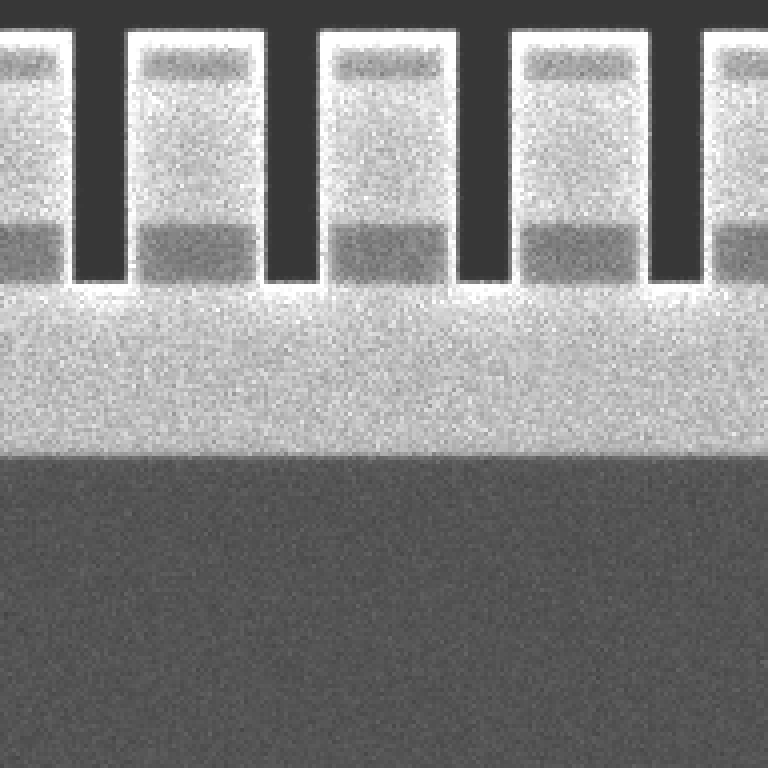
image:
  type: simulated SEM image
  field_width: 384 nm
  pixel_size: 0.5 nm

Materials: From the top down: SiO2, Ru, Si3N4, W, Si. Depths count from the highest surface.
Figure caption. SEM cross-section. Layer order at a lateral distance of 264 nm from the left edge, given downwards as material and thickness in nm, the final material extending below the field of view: SiO2 24, Ru 72, Si3N4 30, W 86, Si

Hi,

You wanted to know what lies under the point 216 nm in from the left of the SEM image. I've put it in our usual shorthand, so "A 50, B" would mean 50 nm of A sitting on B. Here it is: SiO2 24, Ru 72, Si3N4 30, W 86, Si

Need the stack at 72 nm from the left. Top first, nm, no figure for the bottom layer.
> SiO2 24, Ru 72, Si3N4 30, W 86, Si